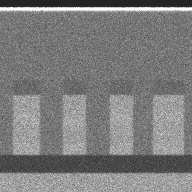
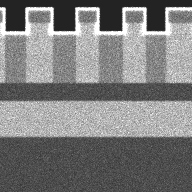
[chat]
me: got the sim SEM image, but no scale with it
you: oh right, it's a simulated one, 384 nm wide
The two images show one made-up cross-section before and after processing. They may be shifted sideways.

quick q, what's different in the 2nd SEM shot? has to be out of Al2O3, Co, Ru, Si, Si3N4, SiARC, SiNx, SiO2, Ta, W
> Si3N4 removed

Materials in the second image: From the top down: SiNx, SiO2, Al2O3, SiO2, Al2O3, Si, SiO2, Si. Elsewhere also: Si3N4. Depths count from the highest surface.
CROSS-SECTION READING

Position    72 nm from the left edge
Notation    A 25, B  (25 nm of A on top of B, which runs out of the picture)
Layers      SiNx 30, SiO2 36, Al2O3 24, SiO2 36, Al2O3 24, Si 36, SiO2 72, Si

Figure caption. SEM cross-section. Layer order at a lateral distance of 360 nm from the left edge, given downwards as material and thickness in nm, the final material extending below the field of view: SiNx 30, SiO2 36, Al2O3 24, SiO2 36, Al2O3 24, Si 36, SiO2 72, Si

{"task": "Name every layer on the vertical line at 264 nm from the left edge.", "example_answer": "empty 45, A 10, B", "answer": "SiNx 30, SiO2 36, Al2O3 24, SiO2 36, Al2O3 24, Si 36, SiO2 72, Si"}